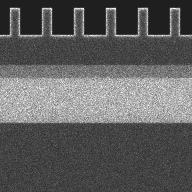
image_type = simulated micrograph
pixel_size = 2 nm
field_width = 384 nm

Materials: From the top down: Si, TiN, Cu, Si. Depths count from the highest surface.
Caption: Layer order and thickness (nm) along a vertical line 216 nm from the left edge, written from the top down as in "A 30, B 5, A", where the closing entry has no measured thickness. Si 114, TiN 26, Cu 90, Si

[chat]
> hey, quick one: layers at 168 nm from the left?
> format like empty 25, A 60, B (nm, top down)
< empty 54, Si 60, TiN 26, Cu 90, Si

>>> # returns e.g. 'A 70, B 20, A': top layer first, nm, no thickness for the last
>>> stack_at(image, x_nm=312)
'empty 54, Si 60, TiN 26, Cu 90, Si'